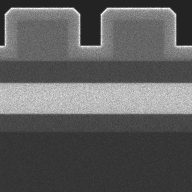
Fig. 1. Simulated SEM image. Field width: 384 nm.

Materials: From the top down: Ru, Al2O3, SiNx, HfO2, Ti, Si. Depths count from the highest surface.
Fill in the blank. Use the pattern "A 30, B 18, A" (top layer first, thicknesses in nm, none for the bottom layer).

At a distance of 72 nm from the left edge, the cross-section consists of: Ru 24, Al2O3 82, SiNx 44, HfO2 62, Ti 36, Si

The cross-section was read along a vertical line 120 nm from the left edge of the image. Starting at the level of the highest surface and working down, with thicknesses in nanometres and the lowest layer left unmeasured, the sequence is Ru 24, Al2O3 82, SiNx 44, HfO2 62, Ti 36, Si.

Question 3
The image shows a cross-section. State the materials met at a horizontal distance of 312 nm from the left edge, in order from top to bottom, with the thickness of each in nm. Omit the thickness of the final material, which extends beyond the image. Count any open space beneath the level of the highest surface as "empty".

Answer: Ru 24, Al2O3 82, SiNx 44, HfO2 62, Ti 36, Si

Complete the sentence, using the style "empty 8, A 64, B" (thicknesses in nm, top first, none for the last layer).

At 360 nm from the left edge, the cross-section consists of empty 76, Ru 24, Al2O3 6, SiNx 44, HfO2 62, Ti 36, Si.